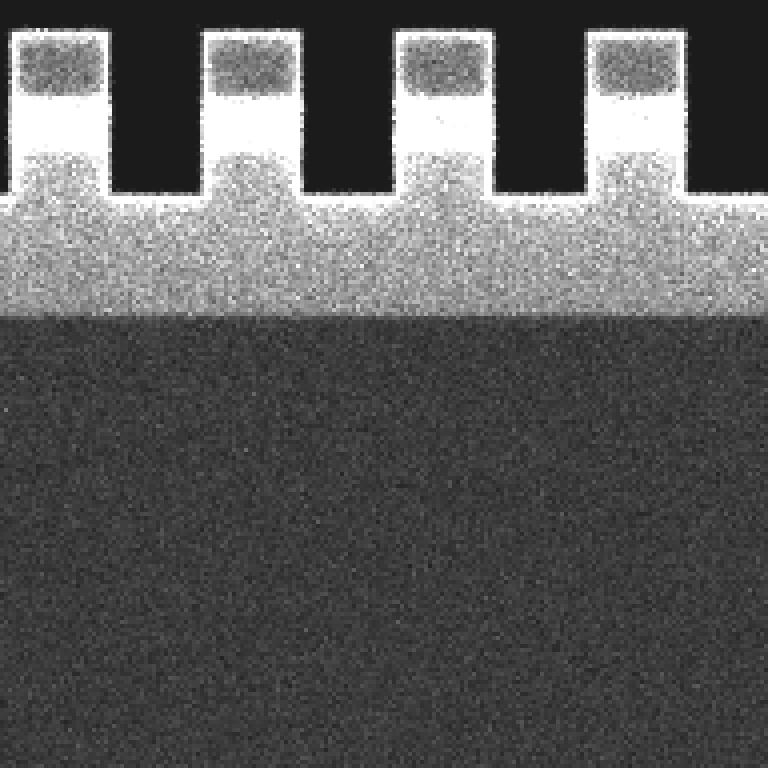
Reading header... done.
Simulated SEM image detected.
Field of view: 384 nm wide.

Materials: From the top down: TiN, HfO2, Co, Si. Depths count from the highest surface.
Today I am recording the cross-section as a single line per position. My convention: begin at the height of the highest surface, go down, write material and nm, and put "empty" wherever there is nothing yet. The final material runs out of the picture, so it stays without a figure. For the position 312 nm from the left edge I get TiN 32, HfO2 28, Co 82, Si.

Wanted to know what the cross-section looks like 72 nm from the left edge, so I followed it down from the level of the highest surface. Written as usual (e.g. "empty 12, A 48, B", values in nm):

empty 82, Co 60, Si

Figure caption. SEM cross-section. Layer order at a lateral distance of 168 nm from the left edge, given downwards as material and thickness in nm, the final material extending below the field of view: empty 82, Co 60, Si